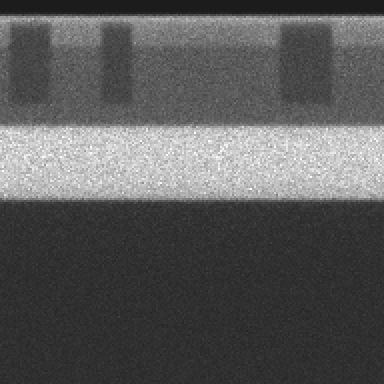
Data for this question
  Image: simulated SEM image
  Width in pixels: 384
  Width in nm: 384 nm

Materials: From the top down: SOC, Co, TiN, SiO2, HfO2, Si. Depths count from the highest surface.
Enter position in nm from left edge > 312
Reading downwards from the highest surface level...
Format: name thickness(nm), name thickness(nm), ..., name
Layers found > SOC 88, SiO2 22, HfO2 74, Si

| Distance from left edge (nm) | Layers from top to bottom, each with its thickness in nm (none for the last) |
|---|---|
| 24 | SOC 88, SiO2 22, HfO2 74, Si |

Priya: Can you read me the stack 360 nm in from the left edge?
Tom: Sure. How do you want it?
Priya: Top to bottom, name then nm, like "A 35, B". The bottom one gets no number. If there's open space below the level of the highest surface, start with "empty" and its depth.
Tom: SOC 6, Co 24, TiN 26, SiO2 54, HfO2 74, Si